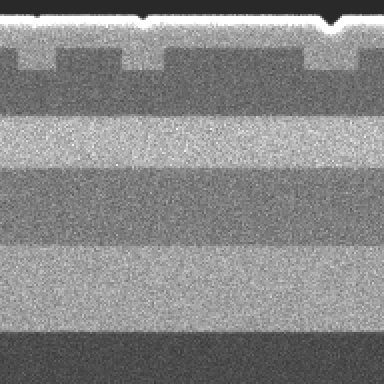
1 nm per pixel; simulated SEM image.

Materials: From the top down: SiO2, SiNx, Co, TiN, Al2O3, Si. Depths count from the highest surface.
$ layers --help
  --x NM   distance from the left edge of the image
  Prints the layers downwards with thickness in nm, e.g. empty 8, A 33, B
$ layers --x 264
SiO2 32, SiNx 68, Co 52, TiN 78, Al2O3 86, Si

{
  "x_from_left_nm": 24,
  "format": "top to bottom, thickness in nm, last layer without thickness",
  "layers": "SiO2 54, SiNx 46, Co 52, TiN 78, Al2O3 86, Si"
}